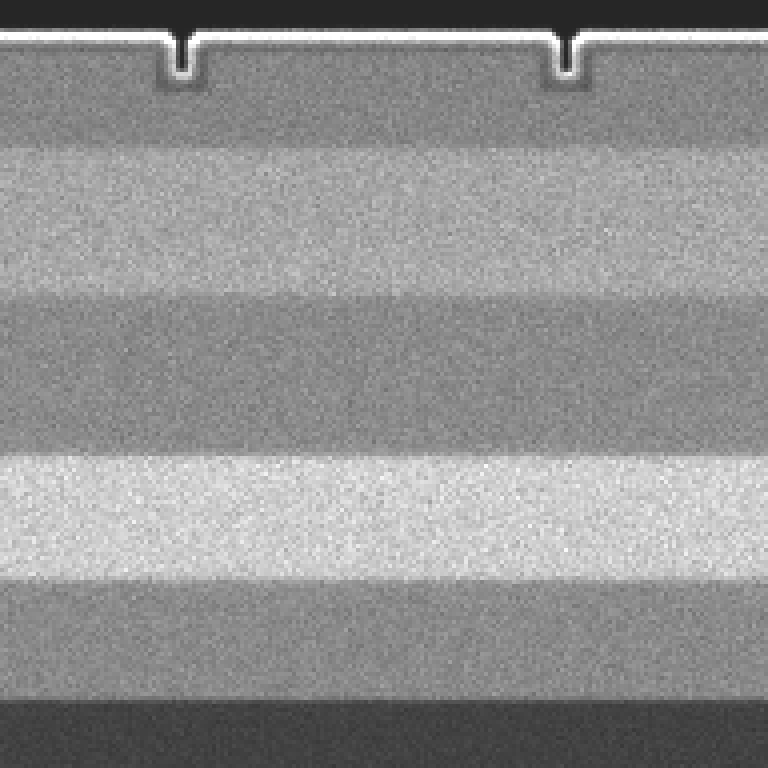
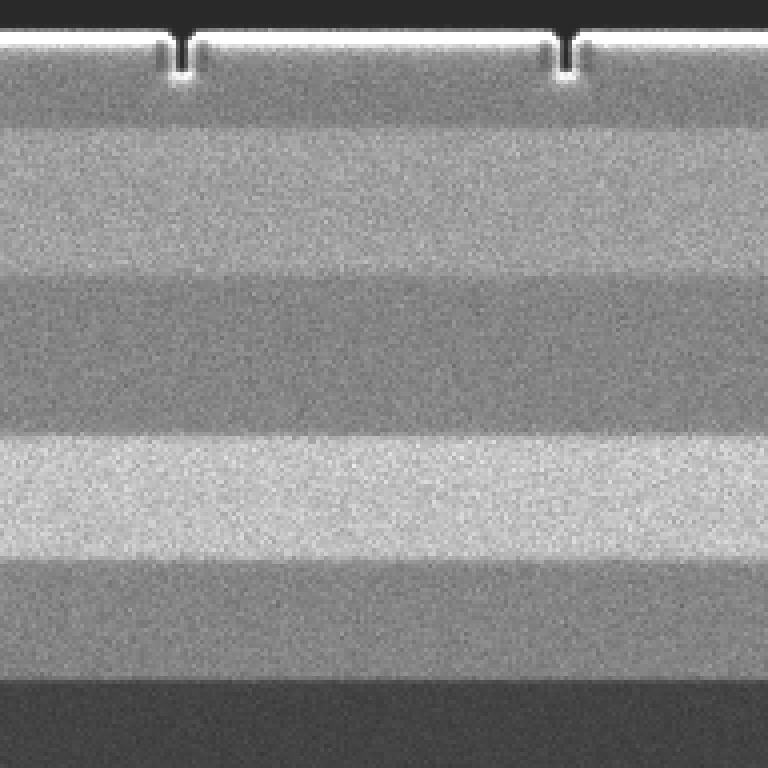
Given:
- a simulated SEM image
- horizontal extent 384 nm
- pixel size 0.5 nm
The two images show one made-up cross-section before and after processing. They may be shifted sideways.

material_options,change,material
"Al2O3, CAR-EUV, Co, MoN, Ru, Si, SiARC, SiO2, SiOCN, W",removed,SiOCN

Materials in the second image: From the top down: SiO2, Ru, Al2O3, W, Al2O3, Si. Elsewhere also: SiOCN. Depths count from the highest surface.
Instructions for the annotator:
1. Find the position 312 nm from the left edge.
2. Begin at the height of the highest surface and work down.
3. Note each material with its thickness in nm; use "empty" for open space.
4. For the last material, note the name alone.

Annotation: SiO2 48, Ru 74, Al2O3 80, W 62, Al2O3 60, Si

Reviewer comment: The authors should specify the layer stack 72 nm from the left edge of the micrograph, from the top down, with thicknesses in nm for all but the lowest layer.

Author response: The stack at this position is SiO2 48, Ru 74, Al2O3 80, W 62, Al2O3 60, Si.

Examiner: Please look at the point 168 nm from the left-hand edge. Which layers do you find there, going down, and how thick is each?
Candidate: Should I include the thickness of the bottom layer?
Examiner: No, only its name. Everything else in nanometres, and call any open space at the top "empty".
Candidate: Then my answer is SiO2 48, Ru 74, Al2O3 80, W 62, Al2O3 60, Si